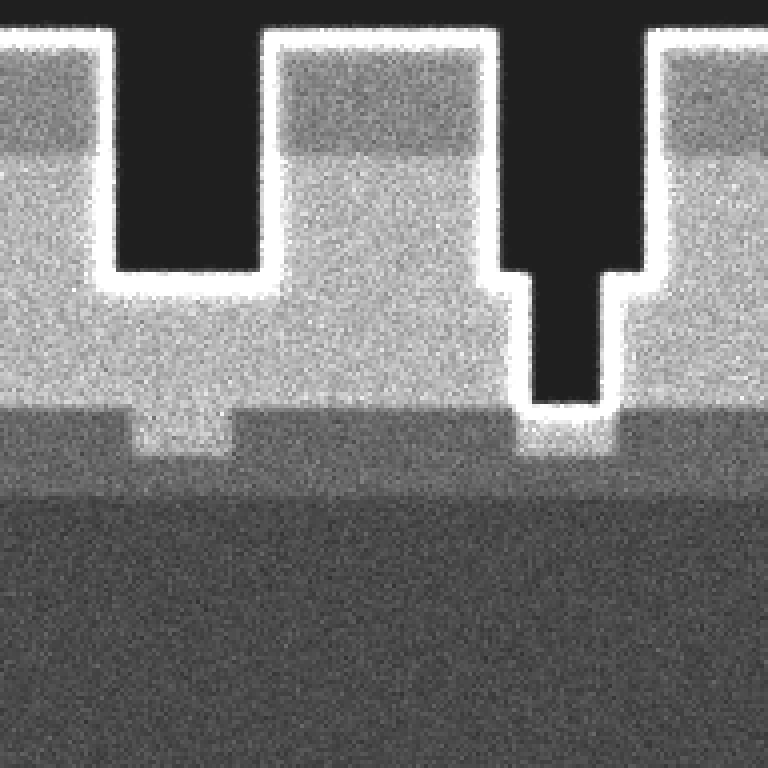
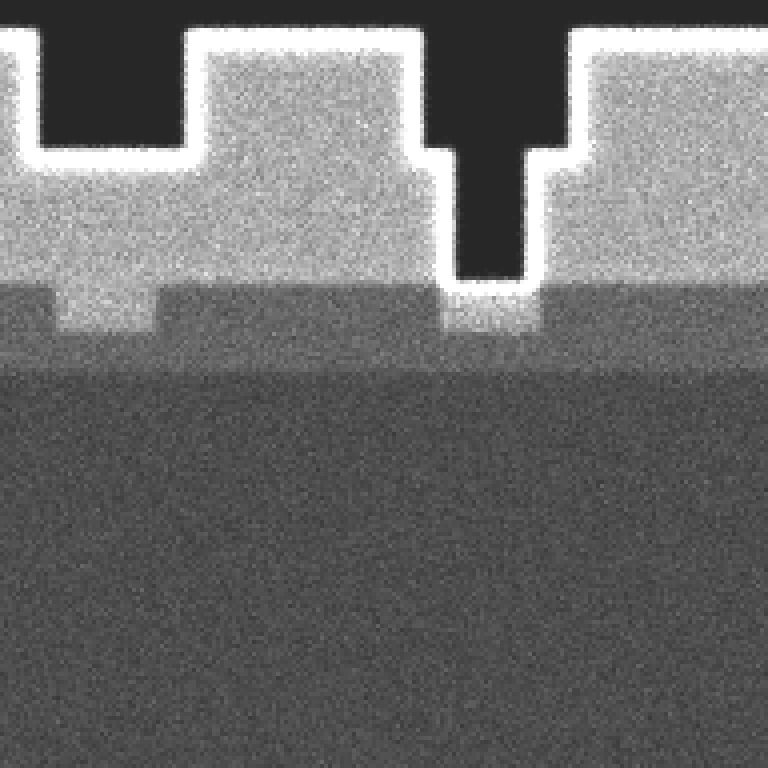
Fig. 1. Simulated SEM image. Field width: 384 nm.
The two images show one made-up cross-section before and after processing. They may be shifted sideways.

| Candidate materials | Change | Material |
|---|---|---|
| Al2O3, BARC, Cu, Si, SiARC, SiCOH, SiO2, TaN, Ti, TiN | removed | SiARC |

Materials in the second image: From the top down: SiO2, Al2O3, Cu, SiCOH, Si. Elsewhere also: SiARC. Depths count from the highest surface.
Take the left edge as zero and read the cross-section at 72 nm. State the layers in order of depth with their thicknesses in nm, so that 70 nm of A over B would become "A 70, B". empty 60, SiO2 56, Al2O3 10, Cu 24, SiCOH 20, Si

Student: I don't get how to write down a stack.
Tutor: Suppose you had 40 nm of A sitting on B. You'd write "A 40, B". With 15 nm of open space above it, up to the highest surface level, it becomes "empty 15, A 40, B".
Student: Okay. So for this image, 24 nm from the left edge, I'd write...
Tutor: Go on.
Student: empty 60, SiO2 56, Al2O3 10, SiCOH 44, Si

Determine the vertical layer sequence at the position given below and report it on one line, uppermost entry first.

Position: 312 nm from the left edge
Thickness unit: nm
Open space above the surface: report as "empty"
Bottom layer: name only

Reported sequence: SiO2 116, Al2O3 10, SiCOH 44, Si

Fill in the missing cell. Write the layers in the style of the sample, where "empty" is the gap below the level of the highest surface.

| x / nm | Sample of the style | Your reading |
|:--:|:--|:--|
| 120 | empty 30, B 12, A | SiO2 116, Al2O3 10, SiCOH 44, Si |